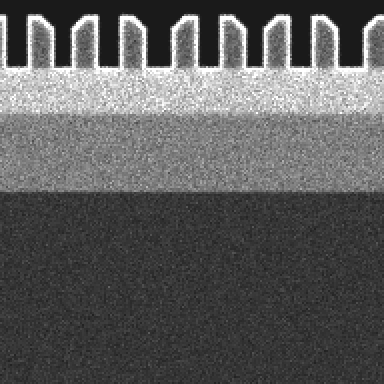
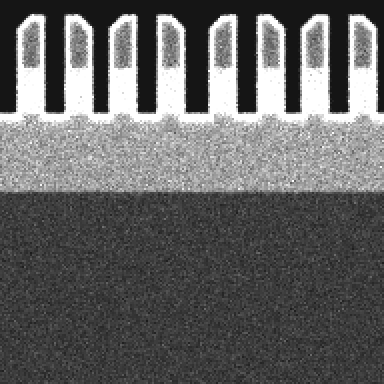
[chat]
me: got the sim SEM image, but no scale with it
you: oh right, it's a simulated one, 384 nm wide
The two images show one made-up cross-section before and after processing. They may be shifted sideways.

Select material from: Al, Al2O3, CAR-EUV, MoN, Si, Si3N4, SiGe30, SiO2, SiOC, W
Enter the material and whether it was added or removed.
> W / removed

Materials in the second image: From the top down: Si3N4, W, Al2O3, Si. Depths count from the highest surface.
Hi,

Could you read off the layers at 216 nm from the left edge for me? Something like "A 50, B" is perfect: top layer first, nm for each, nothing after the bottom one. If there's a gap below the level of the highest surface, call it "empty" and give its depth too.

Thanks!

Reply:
empty 6, Si3N4 46, W 46, Al2O3 78, Si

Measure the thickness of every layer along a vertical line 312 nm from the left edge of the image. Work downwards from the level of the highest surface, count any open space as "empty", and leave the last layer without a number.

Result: empty 2, Si3N4 50, W 46, Al2O3 78, Si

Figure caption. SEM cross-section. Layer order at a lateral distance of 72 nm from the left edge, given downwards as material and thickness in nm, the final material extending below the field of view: Si3N4 52, W 46, Al2O3 78, Si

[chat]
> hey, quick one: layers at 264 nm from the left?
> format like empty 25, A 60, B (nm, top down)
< Si3N4 52, W 46, Al2O3 78, Si